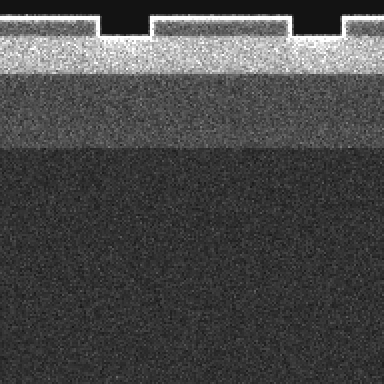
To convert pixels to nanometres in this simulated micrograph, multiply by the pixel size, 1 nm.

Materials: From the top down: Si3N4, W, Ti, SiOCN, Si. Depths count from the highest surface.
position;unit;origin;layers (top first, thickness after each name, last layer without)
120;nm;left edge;empty 20, W 38, Ti 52, SiOCN 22, Si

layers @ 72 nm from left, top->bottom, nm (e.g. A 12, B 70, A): Si3N4 20, W 38, Ti 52, SiOCN 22, Si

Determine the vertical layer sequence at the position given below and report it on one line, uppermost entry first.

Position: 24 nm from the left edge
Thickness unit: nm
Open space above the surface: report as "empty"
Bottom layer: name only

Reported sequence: Si3N4 20, W 38, Ti 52, SiOCN 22, Si